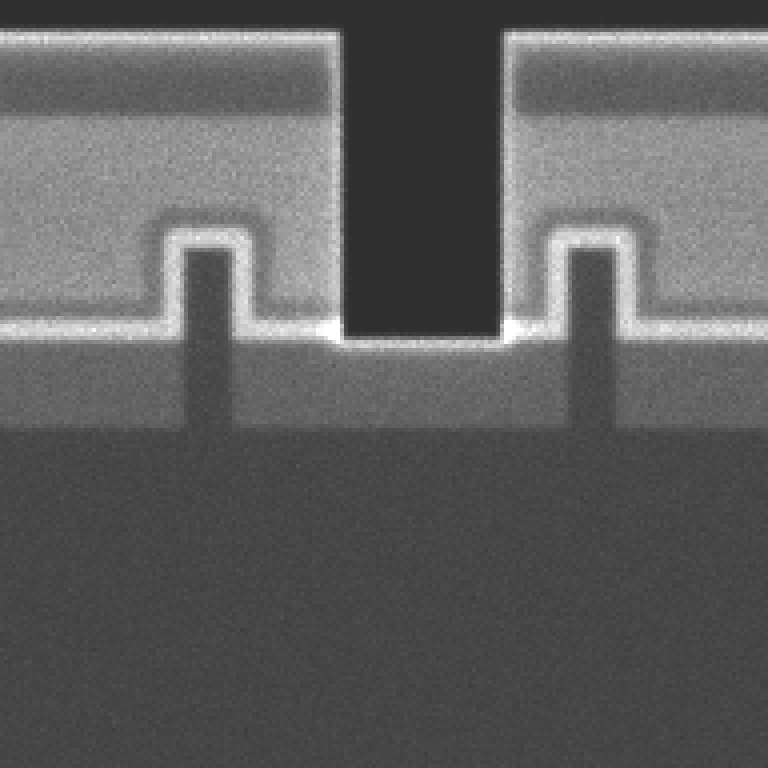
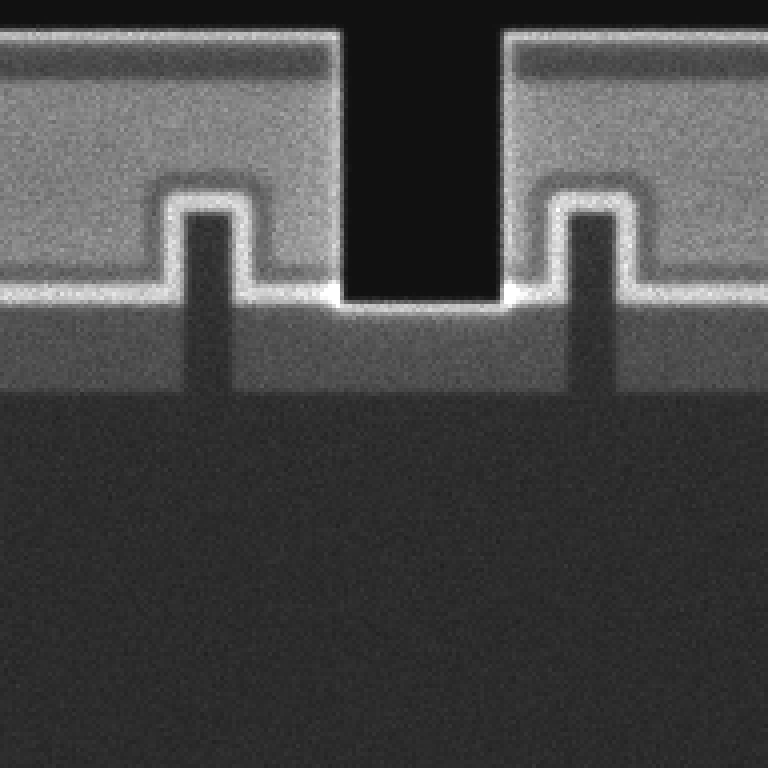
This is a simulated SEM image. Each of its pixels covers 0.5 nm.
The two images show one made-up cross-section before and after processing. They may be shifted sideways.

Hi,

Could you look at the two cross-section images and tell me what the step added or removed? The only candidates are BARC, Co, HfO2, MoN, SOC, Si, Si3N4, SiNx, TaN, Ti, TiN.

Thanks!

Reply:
removed SOC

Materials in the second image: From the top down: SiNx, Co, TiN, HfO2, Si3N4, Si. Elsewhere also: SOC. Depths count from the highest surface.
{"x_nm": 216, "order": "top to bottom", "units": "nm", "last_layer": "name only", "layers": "empty 136, Si3N4 44, Si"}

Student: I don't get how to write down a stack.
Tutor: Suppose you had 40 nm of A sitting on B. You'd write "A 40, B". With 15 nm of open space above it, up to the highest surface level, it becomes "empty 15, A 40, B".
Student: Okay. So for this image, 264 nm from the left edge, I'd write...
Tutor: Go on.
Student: SiNx 24, Co 54, TiN 48, HfO2 10, Si3N4 44, Si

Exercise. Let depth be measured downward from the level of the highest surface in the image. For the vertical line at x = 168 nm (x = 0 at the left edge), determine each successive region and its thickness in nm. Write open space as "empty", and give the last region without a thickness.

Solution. SiNx 24, Co 92, TiN 10, HfO2 10, Si3N4 44, Si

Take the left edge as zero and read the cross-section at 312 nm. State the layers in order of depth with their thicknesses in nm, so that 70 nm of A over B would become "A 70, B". SiNx 24, Co 46, TiN 10, HfO2 56, Si3N4 44, Si